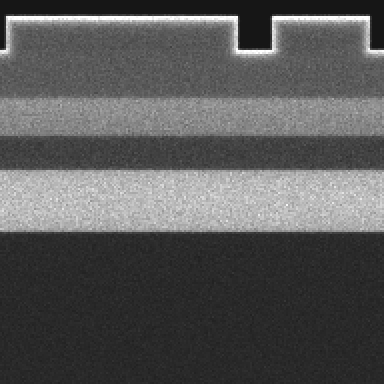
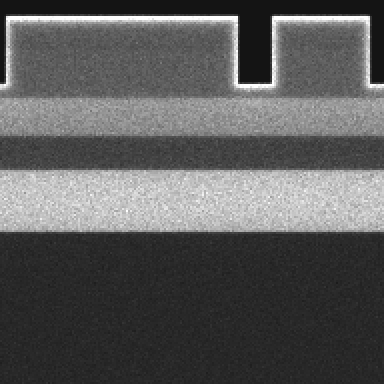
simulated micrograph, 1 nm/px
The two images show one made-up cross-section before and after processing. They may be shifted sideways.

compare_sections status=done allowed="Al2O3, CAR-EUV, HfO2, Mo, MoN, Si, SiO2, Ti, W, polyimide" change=removed material="Al2O3"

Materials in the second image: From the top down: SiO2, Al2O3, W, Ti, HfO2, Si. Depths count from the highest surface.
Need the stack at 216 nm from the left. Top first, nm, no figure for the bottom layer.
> SiO2 34, Al2O3 48, W 38, Ti 34, HfO2 62, Si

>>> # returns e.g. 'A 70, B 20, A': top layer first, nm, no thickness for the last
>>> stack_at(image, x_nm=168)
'SiO2 34, Al2O3 48, W 38, Ti 34, HfO2 62, Si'